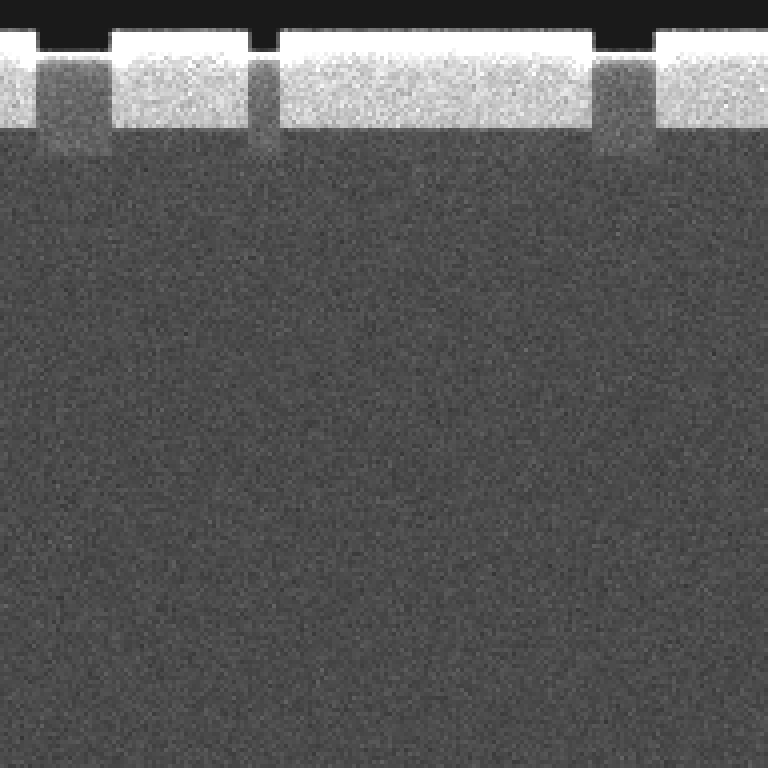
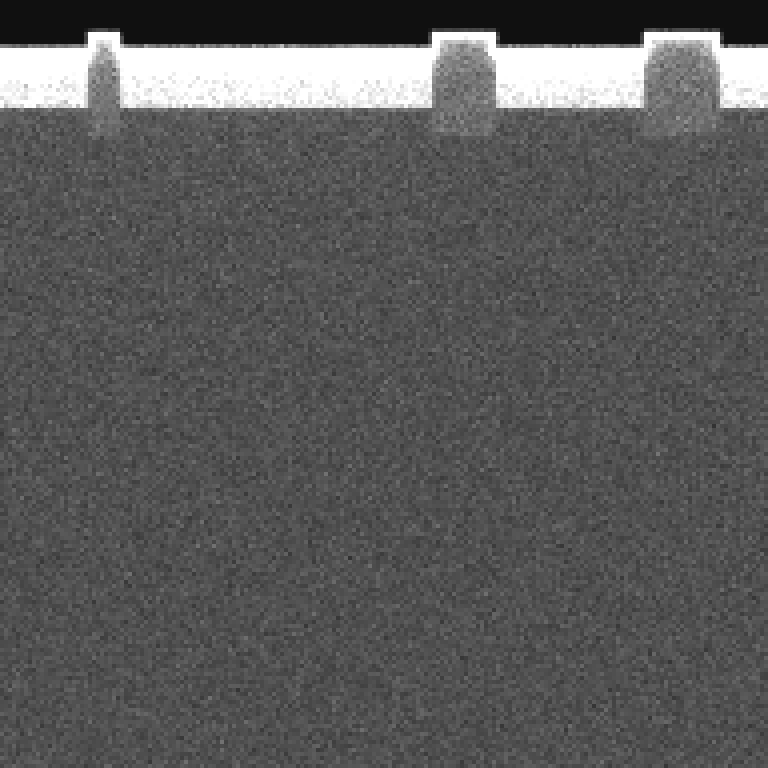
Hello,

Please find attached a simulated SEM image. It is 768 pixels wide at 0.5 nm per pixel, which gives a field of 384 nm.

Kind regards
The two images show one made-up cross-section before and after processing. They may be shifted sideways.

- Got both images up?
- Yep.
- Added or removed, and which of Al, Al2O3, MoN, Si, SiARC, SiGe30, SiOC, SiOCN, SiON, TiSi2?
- removed, Al2O3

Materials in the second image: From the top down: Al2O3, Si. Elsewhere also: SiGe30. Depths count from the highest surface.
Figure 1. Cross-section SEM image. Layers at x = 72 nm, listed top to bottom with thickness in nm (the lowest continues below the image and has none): empty 8, Al2O3 30, Si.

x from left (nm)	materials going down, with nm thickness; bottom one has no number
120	empty 8, Al2O3 30, Si